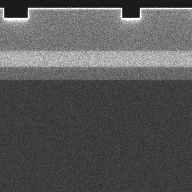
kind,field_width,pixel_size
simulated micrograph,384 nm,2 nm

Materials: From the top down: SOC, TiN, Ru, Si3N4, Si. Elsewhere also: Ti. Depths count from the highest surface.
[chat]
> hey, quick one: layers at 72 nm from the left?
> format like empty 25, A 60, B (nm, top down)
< Ti 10, TiN 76, Ru 32, Si3N4 26, Si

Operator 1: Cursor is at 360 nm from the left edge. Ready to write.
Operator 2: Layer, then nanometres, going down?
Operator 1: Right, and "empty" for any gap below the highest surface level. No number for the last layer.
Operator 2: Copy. Ti 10, TiN 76, Ru 32, Si3N4 26, Si